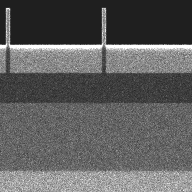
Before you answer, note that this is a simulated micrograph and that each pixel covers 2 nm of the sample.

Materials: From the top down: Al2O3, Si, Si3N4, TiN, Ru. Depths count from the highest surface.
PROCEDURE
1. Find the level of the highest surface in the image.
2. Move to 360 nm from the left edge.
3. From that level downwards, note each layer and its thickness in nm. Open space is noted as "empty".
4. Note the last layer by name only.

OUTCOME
empty 74, Al2O3 56, Si 60, Si3N4 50, TiN 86, Ru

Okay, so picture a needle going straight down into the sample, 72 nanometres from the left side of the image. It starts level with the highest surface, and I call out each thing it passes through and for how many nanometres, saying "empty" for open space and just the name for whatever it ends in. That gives empty 74, Al2O3 56, Si 60, Si3N4 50, TiN 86, Ru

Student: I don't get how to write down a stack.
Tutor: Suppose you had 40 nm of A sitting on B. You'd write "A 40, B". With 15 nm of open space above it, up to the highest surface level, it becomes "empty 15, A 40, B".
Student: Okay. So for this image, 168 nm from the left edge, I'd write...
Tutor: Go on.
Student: empty 74, Al2O3 56, Si 60, Si3N4 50, TiN 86, Ru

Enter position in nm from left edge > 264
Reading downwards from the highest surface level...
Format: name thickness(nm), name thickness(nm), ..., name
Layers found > empty 74, Al2O3 56, Si 60, Si3N4 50, TiN 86, Ru